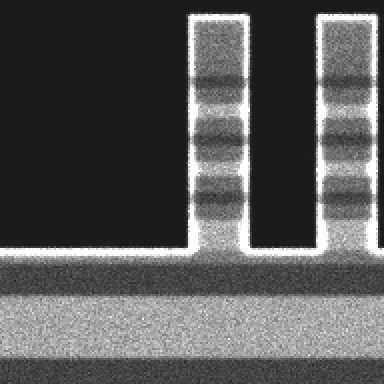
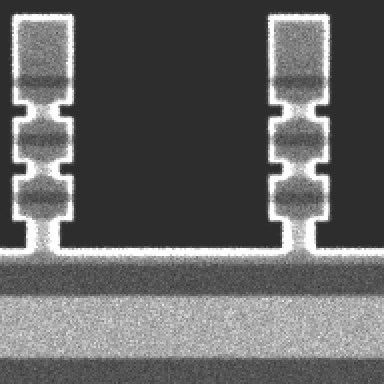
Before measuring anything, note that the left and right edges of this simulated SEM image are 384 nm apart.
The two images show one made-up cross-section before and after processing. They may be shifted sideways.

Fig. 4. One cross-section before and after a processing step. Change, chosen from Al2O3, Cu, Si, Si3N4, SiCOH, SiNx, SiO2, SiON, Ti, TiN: Al2O3 removed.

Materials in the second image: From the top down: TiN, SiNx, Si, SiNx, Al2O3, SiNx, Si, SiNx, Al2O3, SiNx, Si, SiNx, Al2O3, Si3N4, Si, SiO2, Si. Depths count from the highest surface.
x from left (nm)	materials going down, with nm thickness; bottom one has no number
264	empty 234, Si3N4 14, Si 32, SiO2 62, Si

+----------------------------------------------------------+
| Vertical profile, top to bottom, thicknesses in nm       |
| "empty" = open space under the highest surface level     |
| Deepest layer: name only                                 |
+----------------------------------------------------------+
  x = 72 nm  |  empty 234, Si3N4 14, Si 32, SiO2 62, Si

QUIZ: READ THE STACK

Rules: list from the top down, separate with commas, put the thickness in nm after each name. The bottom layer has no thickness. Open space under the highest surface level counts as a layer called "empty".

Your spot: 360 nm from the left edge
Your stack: empty 234, Si3N4 14, Si 32, SiO2 62, Si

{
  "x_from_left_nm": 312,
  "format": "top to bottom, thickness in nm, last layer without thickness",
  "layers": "TiN 44, SiNx 16, Si 12, SiNx 16, Al2O3 14, SiNx 16, Si 12, SiNx 16, Al2O3 14, SiNx 16, Si 12, SiNx 16, Al2O3 30, Si3N4 14, Si 32, SiO2 62, Si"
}